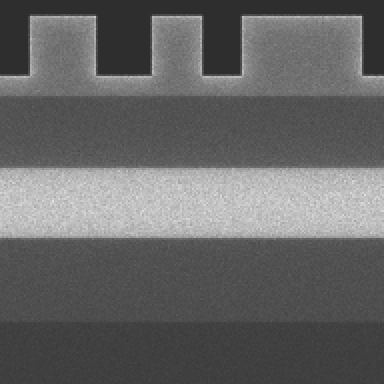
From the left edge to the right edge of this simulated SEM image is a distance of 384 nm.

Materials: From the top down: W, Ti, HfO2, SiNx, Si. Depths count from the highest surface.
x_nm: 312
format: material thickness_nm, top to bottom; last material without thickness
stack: W 80, Ti 72, HfO2 70, SiNx 84, Si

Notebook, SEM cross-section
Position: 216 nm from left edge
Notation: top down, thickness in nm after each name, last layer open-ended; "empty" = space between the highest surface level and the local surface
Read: empty 60, W 20, Ti 72, HfO2 70, SiNx 84, Si